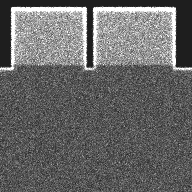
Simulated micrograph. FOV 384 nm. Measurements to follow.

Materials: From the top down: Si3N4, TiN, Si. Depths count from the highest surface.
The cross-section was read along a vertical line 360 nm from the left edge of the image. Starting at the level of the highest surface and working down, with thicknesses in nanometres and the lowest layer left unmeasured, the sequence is empty 120, Si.